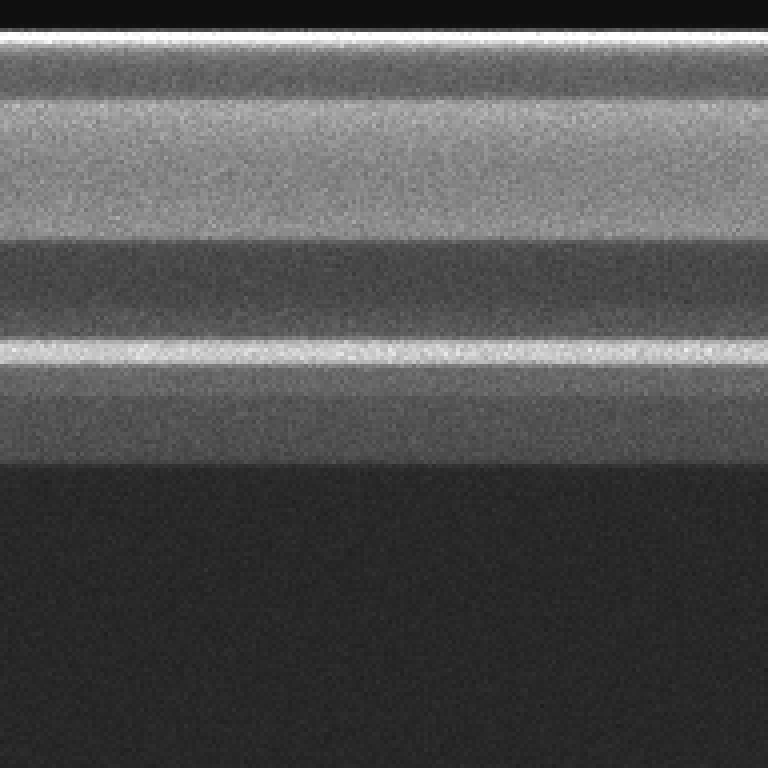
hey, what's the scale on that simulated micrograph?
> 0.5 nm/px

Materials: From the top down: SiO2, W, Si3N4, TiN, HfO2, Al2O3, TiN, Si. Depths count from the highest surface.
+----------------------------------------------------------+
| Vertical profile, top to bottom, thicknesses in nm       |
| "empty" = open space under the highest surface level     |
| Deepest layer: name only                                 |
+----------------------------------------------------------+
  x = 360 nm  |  SiO2 34, W 70, Si3N4 34, TiN 16, HfO2 12, Al2O3 16, TiN 34, Si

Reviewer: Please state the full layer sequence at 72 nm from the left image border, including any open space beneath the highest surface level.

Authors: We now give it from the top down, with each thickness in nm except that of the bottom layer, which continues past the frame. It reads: SiO2 34, W 70, Si3N4 34, TiN 16, HfO2 12, Al2O3 16, TiN 34, Si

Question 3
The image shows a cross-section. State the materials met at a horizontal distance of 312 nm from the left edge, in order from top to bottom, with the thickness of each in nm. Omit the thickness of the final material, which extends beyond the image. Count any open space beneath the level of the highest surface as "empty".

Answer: SiO2 34, W 70, Si3N4 34, TiN 16, HfO2 12, Al2O3 16, TiN 34, Si